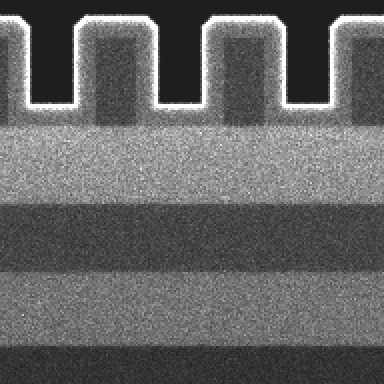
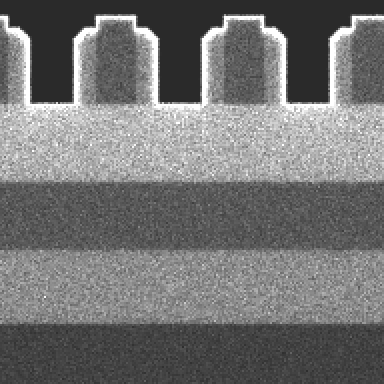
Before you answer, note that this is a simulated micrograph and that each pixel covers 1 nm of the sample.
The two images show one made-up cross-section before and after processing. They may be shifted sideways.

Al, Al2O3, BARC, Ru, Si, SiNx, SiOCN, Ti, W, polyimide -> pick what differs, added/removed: Al2O3 removed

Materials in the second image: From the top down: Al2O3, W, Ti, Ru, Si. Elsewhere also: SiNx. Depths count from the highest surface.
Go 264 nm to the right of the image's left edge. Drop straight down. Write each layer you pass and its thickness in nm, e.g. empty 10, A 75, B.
empty 12, Al2O3 76, W 78, Ti 68, Ru 74, Si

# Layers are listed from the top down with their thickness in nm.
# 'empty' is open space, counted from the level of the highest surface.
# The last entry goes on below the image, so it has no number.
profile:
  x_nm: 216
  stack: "empty 12, Al2O3 76, W 78, Ti 68, Ru 74, Si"